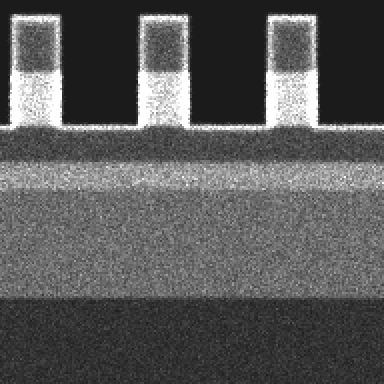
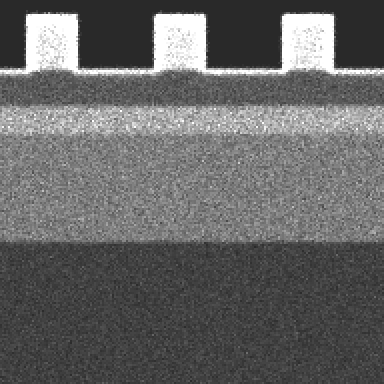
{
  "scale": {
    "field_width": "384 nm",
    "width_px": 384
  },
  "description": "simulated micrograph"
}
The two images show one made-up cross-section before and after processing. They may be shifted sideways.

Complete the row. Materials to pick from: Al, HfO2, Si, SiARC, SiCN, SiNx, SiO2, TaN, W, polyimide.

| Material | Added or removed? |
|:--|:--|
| SiARC | removed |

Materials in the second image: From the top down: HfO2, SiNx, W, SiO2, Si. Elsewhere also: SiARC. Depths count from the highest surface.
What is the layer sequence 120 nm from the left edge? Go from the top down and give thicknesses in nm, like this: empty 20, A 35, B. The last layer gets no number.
empty 54, SiNx 36, W 28, SiO2 108, Si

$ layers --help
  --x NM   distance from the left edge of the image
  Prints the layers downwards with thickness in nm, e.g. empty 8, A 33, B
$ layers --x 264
empty 54, SiNx 36, W 28, SiO2 108, Si